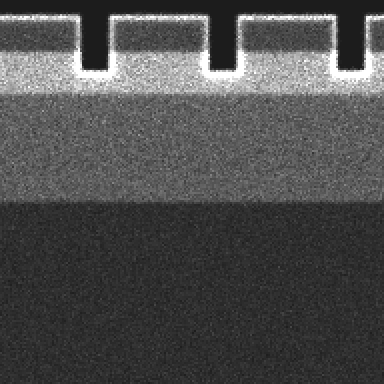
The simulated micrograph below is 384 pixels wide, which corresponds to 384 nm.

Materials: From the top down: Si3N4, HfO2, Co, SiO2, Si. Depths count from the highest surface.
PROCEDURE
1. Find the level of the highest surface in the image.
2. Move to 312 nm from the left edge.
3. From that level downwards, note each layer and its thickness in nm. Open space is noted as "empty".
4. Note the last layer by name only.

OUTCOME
Si3N4 36, HfO2 42, Co 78, SiO2 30, Si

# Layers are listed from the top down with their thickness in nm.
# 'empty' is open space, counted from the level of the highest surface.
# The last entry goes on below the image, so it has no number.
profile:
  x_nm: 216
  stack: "empty 56, HfO2 22, Co 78, SiO2 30, Si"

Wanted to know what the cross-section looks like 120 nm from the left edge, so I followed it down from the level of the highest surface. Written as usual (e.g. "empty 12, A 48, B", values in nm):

Si3N4 36, HfO2 42, Co 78, SiO2 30, Si